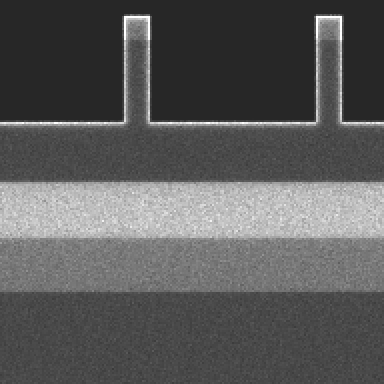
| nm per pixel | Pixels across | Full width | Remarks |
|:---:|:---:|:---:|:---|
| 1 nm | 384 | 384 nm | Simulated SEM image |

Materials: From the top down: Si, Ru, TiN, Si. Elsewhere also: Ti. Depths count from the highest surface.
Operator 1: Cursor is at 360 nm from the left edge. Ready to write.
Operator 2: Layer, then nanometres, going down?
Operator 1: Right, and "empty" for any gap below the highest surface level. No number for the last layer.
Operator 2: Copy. empty 106, Si 60, Ru 56, TiN 54, Si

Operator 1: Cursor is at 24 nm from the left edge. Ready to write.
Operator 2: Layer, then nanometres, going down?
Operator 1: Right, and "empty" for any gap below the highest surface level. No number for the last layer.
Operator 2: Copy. empty 106, Si 60, Ru 56, TiN 54, Si